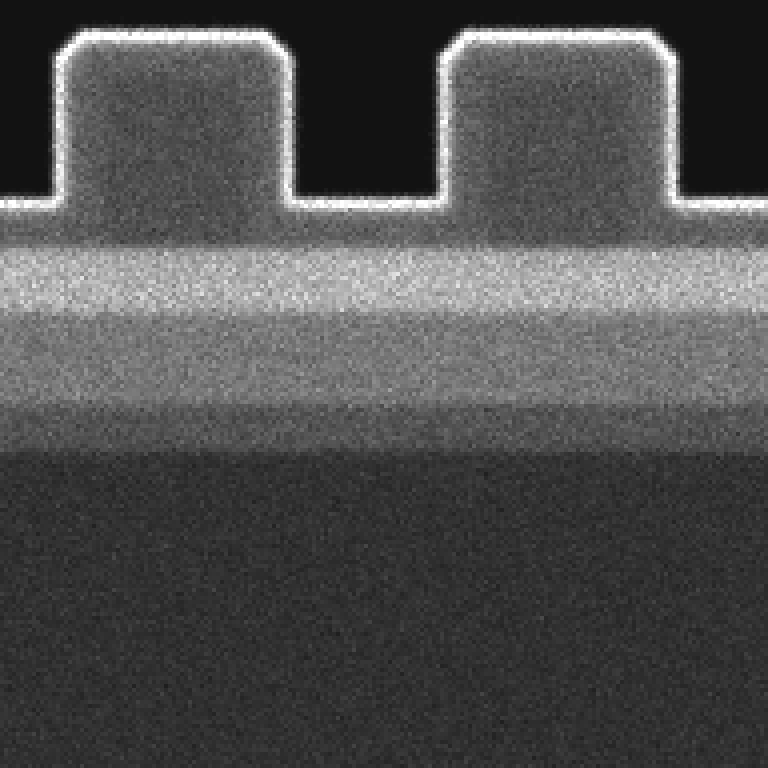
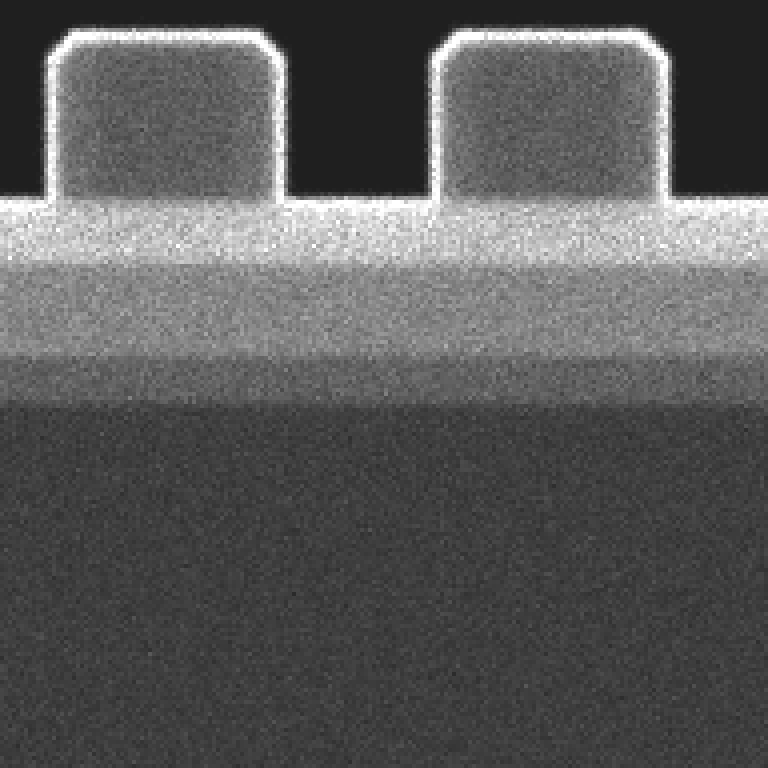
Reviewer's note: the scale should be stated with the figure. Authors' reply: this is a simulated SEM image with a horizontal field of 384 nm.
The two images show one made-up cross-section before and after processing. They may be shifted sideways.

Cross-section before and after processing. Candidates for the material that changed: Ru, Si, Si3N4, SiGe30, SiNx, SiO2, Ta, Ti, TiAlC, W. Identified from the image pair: Si3N4 (removed).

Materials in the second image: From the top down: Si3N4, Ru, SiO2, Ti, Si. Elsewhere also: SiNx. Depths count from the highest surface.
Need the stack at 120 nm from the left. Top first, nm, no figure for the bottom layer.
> Si3N4 84, Ru 32, SiO2 46, Ti 24, Si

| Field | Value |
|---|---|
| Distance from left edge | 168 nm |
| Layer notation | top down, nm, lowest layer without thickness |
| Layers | empty 84, Ru 32, SiO2 46, Ti 24, Si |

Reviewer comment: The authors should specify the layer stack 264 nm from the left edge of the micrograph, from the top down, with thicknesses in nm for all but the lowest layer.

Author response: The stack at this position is SiNx 84, Ru 32, SiO2 46, Ti 24, Si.